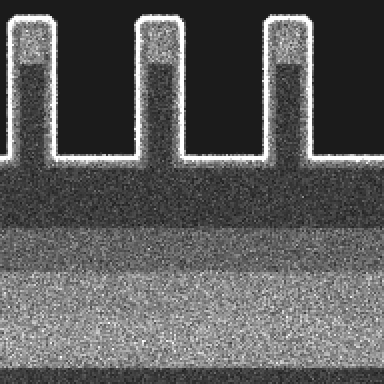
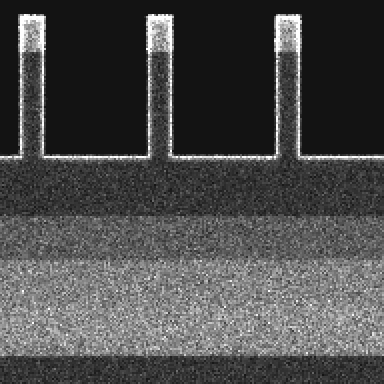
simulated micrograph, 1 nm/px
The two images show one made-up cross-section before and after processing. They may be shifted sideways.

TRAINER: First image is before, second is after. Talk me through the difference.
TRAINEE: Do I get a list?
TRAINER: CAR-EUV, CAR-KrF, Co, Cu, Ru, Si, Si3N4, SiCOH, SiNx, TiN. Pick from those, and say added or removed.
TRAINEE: removed: Si3N4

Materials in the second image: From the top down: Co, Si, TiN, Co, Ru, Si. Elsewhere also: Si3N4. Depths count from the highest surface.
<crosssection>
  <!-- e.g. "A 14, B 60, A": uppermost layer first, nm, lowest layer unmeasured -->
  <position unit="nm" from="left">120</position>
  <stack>empty 140, Si 60, TiN 44, Co 44, Ru 52, Si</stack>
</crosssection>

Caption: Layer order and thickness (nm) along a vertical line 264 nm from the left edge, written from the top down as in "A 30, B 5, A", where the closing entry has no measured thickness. empty 140, Si 60, TiN 44, Co 44, Ru 52, Si